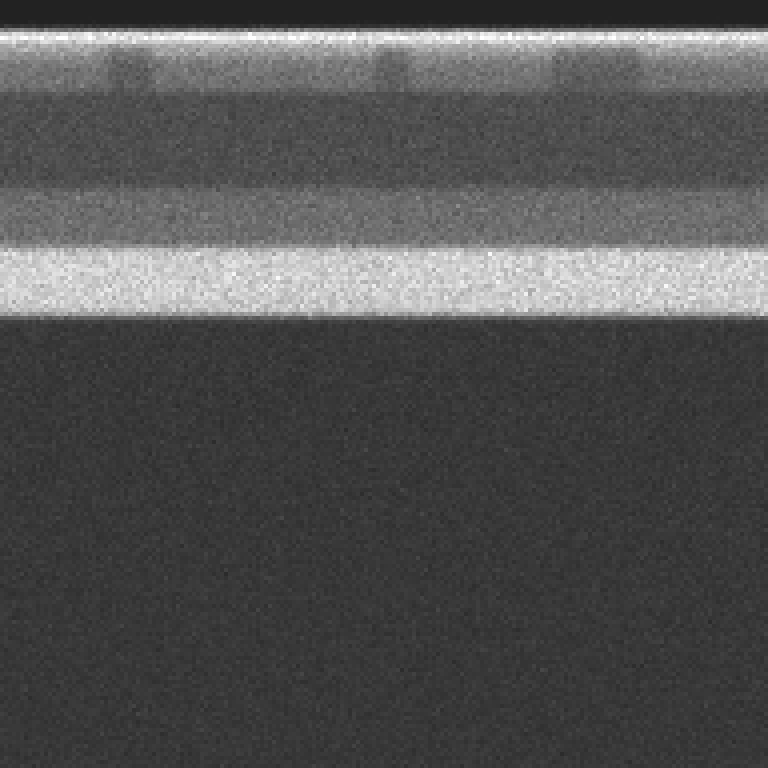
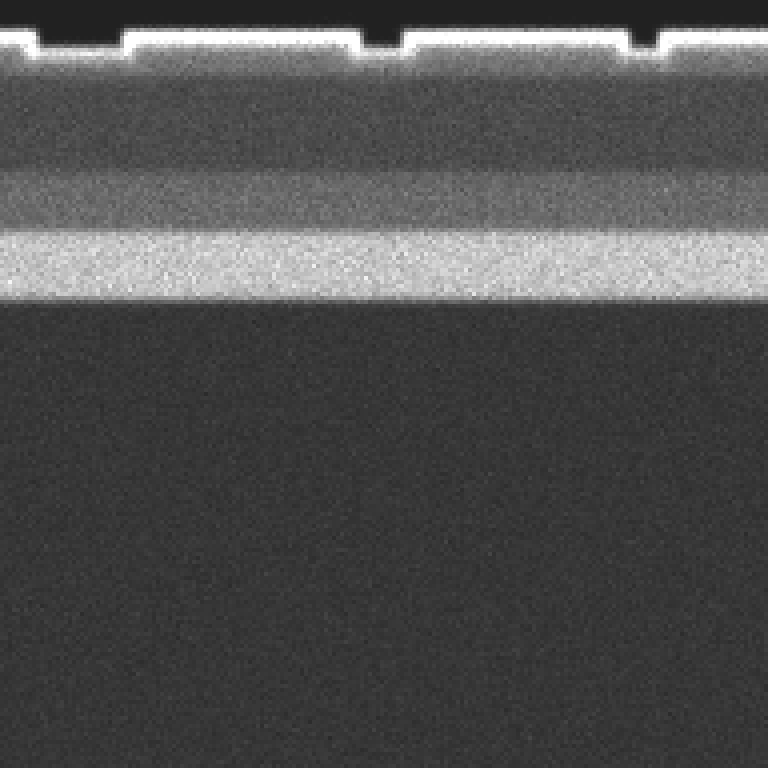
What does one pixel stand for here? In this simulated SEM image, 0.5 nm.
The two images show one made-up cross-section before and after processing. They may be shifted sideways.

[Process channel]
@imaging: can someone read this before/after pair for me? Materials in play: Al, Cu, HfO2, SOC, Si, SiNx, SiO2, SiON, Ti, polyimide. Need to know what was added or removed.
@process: SOC removed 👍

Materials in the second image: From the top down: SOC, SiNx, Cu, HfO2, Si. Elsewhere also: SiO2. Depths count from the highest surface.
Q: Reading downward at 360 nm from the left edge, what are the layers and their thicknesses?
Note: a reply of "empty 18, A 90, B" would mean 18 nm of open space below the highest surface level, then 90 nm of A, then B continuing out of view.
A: SiO2 22, SiNx 48, Cu 30, HfO2 34, Si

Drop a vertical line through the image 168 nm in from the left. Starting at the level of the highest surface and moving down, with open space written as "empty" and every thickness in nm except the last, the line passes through SiO2 22, SiNx 48, Cu 30, HfO2 34, Si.